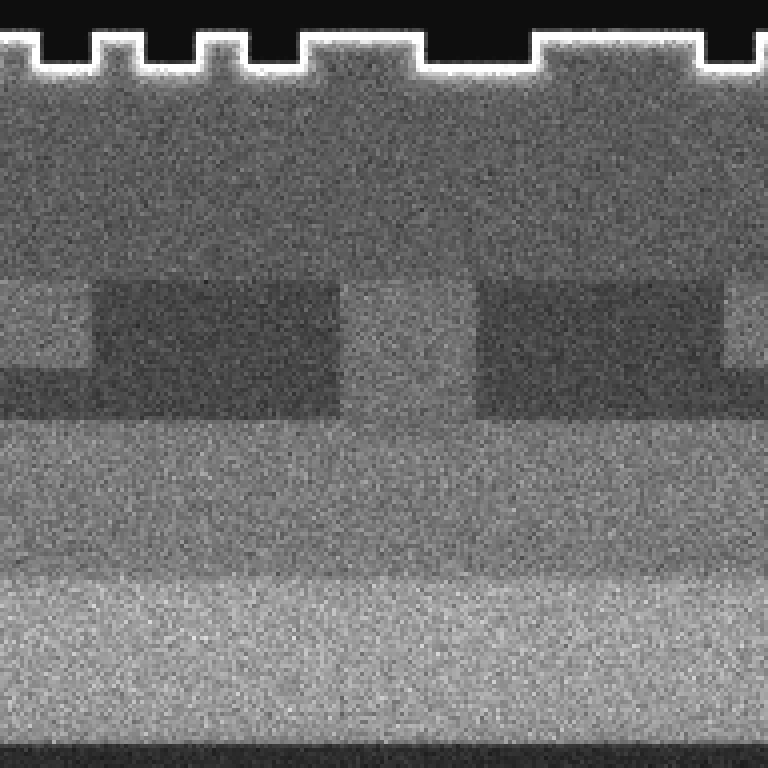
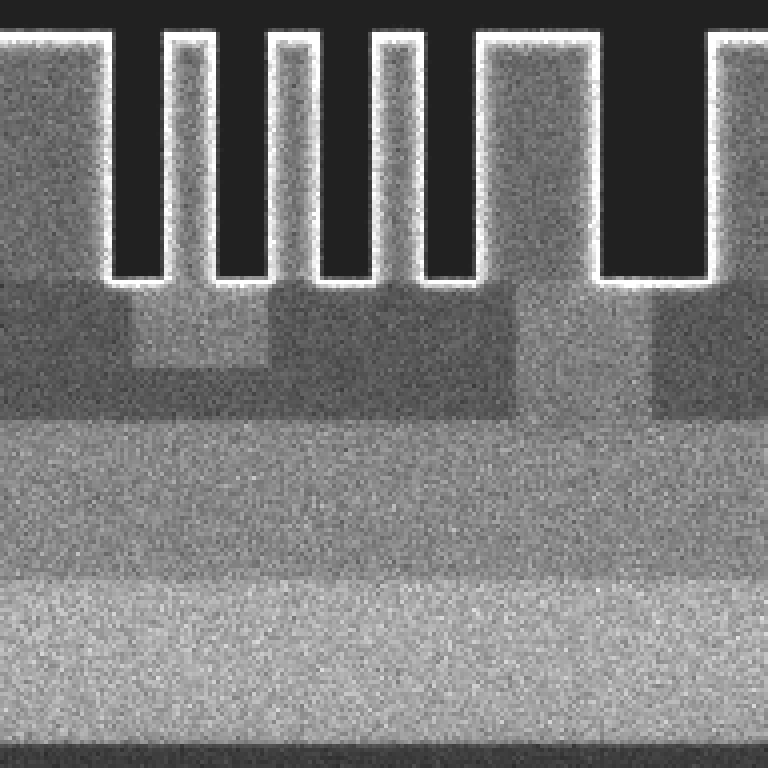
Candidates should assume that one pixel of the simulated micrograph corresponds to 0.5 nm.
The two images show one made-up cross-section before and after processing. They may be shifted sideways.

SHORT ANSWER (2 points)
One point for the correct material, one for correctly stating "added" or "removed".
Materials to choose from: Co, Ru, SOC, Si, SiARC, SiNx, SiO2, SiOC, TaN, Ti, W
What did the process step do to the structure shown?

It removed SOC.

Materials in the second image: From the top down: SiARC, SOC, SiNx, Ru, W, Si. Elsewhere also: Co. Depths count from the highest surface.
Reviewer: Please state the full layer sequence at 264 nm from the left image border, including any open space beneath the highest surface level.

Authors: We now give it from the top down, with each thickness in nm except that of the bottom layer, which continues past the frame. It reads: SiARC 16, SOC 108, Co 78, Ru 72, W 82, Si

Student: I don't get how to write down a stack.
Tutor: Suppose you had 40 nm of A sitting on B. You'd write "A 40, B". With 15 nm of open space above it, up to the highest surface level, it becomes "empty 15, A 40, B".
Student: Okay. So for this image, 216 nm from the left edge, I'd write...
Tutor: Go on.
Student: empty 124, SiNx 70, Ru 80, W 82, Si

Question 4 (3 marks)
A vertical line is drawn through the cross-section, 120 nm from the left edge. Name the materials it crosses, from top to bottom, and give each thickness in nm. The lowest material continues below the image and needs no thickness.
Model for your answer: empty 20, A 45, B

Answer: empty 124, Co 44, SiNx 26, Ru 80, W 82, Si